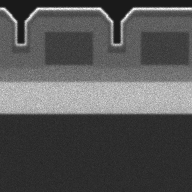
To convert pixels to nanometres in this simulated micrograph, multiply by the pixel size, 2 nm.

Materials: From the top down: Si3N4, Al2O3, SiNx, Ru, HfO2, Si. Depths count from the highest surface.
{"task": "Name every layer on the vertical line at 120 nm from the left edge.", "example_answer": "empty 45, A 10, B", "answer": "Si3N4 18, Al2O3 30, SiNx 66, Ru 34, HfO2 64, Si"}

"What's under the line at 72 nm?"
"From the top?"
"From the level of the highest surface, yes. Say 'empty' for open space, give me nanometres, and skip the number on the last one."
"empty 2, Si3N4 18, Al2O3 100, Ru 28, HfO2 64, Si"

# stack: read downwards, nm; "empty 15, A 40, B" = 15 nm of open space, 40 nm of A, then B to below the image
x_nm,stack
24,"empty 18, Si3N4 72, Al2O3 30, Ru 28, HfO2 64, Si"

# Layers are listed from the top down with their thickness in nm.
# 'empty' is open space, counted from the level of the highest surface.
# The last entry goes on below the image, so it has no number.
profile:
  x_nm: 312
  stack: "Si3N4 18, Al2O3 30, SiNx 66, Ru 34, HfO2 64, Si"